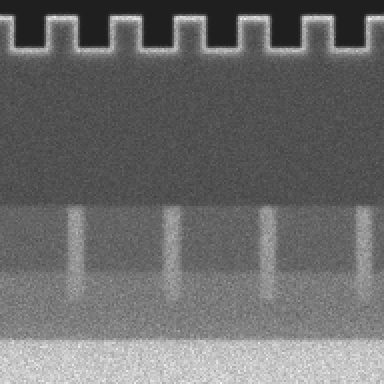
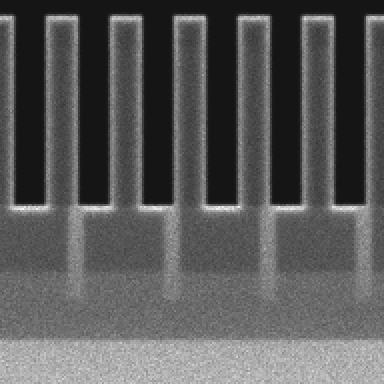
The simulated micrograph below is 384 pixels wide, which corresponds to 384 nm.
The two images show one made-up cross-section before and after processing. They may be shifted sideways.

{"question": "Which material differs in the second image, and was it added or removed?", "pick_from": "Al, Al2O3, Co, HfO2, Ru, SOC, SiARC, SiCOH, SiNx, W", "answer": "SOC, removed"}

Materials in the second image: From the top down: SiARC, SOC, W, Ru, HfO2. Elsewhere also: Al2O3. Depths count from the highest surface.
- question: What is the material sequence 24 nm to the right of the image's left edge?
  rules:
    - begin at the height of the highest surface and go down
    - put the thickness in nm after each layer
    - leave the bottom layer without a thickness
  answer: empty 190, Al2O3 66, Ru 68, HfO2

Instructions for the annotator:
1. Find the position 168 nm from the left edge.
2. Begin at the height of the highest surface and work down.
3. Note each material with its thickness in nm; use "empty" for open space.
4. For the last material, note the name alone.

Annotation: empty 190, W 94, Ru 40, HfO2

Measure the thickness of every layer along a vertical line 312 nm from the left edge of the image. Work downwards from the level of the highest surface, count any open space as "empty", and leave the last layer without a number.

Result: SiARC 32, SOC 158, Al2O3 66, Ru 68, HfO2